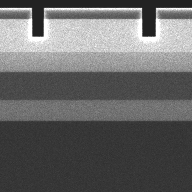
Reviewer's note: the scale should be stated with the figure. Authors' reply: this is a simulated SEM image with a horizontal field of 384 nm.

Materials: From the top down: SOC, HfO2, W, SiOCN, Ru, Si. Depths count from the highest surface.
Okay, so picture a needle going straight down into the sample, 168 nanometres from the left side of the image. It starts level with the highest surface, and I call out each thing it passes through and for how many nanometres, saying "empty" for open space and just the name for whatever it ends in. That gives SOC 22, HfO2 66, W 40, SiOCN 56, Ru 42, Si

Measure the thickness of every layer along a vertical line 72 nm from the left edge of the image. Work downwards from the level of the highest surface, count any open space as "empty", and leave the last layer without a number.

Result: empty 58, HfO2 30, W 40, SiOCN 56, Ru 42, Si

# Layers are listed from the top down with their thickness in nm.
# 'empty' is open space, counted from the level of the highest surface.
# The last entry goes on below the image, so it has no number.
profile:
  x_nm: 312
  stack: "SOC 22, HfO2 66, W 40, SiOCN 56, Ru 42, Si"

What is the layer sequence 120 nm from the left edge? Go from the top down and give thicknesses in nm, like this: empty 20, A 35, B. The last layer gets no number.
SOC 22, HfO2 66, W 40, SiOCN 56, Ru 42, Si